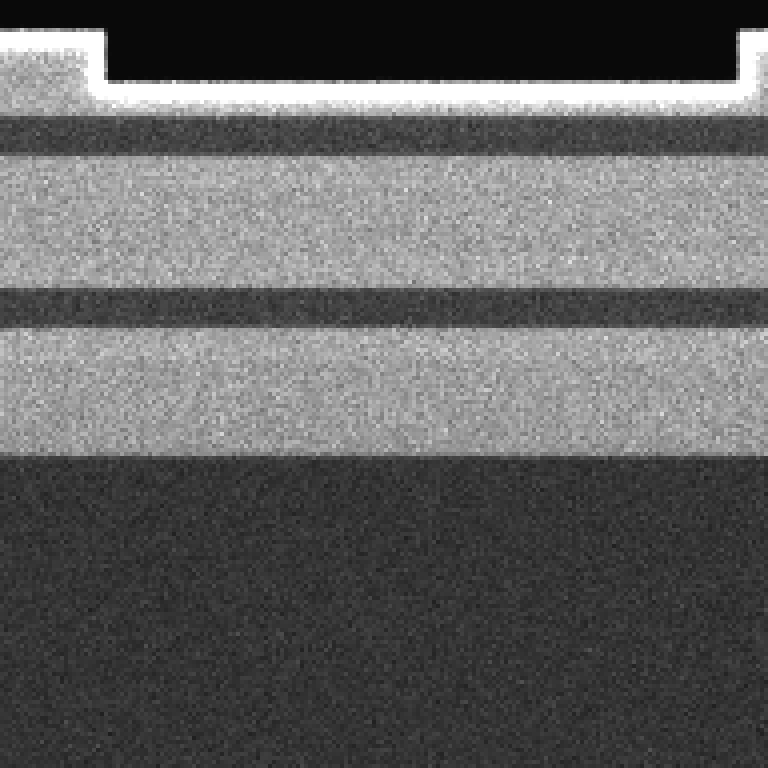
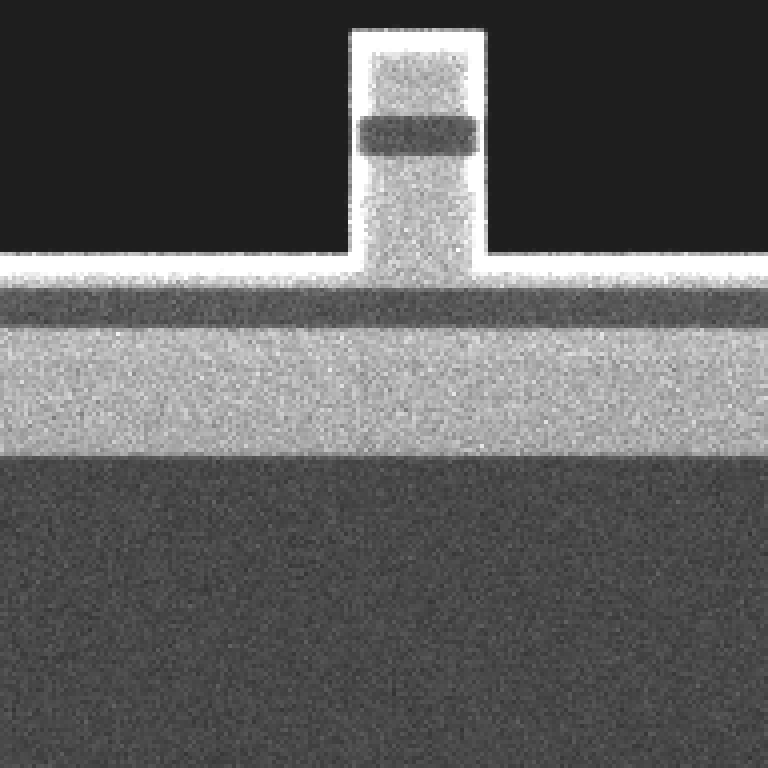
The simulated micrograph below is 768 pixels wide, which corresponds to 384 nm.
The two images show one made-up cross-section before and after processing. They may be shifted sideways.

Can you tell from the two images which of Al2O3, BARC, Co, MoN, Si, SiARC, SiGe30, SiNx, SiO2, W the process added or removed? Yes, it removed Al2O3 and Co and SiGe30.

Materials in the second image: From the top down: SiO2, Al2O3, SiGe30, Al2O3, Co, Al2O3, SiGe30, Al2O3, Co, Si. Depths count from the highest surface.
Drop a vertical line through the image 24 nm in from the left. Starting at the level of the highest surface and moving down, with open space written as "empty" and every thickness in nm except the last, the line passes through empty 112, Al2O3 16, SiGe30 20, Al2O3 16, Co 48, Si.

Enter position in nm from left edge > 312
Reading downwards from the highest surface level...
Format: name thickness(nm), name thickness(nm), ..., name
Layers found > empty 112, Al2O3 16, SiGe30 20, Al2O3 16, Co 48, Si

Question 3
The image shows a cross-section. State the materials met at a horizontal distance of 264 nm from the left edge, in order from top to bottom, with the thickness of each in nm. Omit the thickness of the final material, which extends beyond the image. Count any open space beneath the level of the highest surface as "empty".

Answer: empty 112, Al2O3 16, SiGe30 20, Al2O3 16, Co 48, Si